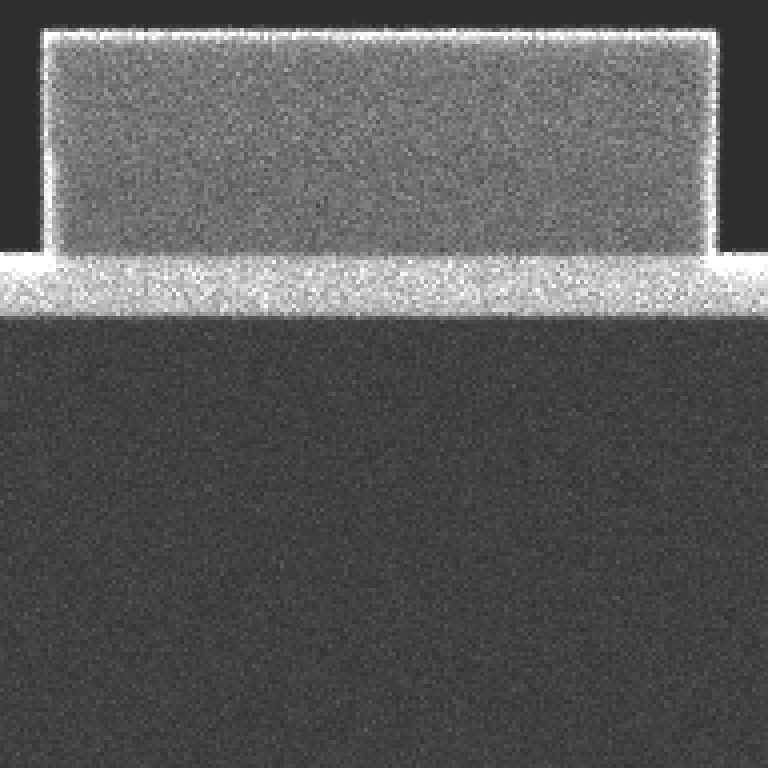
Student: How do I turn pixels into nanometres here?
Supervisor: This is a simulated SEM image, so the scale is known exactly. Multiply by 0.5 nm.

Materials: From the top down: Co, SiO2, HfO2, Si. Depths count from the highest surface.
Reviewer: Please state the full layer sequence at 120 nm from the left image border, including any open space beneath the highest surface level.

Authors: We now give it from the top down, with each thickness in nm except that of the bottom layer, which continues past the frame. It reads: Co 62, SiO2 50, HfO2 30, Si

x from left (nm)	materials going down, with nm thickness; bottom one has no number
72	Co 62, SiO2 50, HfO2 30, Si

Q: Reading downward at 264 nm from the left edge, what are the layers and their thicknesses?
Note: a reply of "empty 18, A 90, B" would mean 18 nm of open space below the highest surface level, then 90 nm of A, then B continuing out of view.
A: Co 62, SiO2 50, HfO2 30, Si